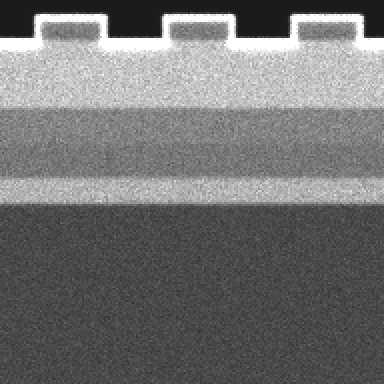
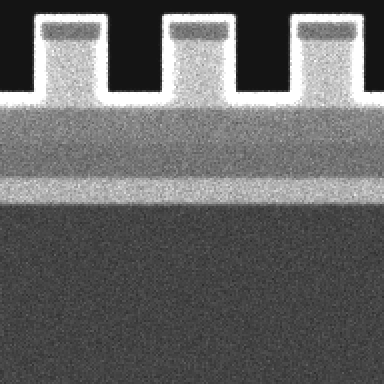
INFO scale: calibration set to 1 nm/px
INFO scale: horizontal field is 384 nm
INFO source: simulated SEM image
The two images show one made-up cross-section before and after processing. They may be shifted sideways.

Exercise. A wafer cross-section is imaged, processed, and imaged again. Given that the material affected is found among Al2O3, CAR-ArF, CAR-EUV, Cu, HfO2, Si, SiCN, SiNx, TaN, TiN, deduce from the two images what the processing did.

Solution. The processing removed Al2O3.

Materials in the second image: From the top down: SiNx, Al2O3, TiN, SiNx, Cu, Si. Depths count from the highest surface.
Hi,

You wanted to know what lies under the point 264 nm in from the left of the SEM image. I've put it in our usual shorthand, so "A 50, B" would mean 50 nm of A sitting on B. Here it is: empty 78, Al2O3 14, TiN 36, SiNx 34, Cu 26, Si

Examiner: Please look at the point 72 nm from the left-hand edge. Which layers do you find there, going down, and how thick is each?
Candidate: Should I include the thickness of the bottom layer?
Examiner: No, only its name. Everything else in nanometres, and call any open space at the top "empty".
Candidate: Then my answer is SiNx 24, Al2O3 68, TiN 36, SiNx 34, Cu 26, Si